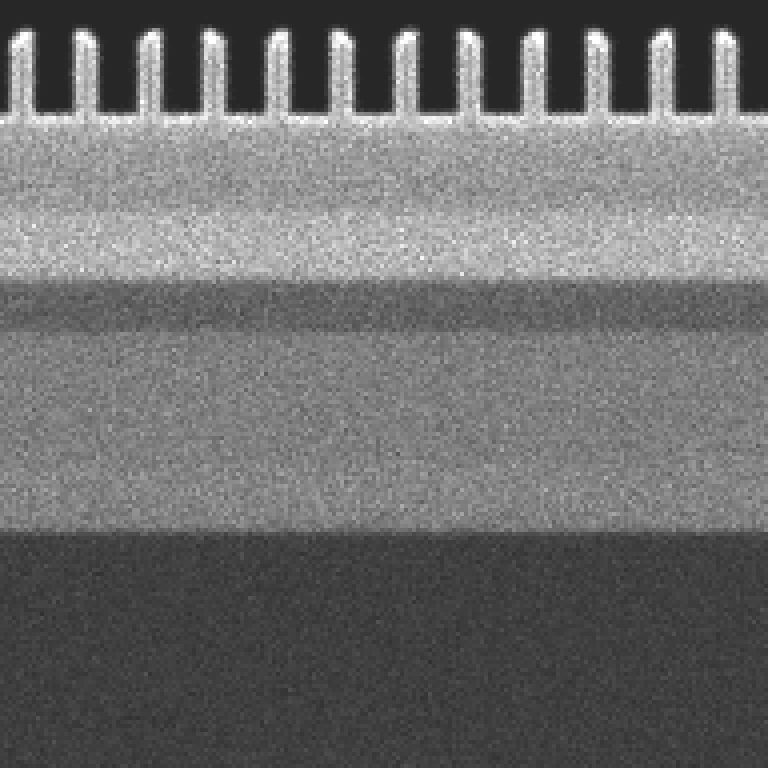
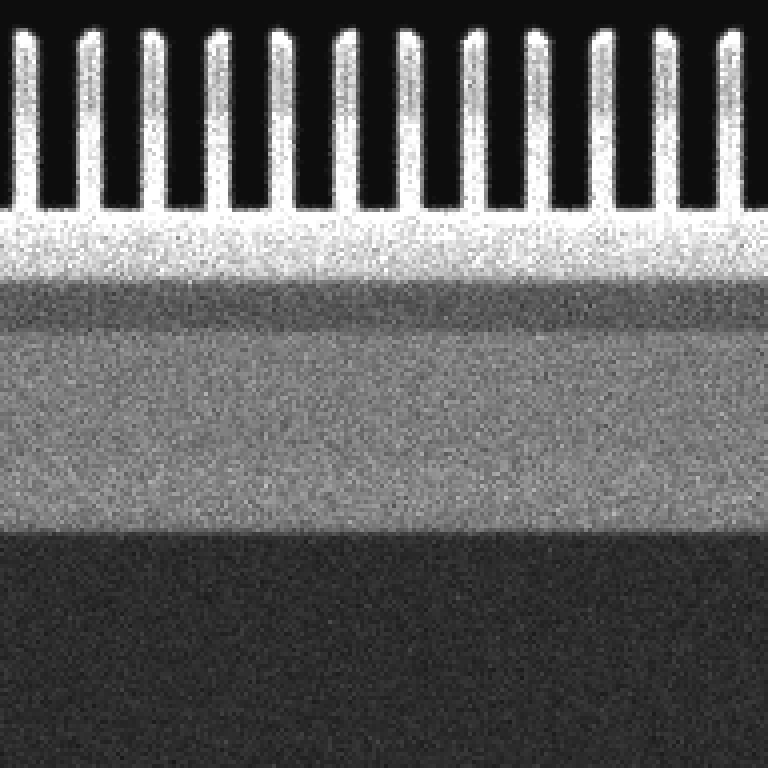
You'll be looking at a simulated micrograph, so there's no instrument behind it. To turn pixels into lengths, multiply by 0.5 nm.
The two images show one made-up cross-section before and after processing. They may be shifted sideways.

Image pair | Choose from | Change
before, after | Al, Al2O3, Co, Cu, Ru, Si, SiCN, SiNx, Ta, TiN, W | Ru (removed)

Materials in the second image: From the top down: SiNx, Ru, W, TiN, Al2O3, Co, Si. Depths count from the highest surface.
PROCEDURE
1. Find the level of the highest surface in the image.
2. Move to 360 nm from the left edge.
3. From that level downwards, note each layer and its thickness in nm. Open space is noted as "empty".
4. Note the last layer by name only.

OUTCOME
empty 4, SiNx 38, Ru 48, W 34, TiN 26, Al2O3 66, Co 34, Si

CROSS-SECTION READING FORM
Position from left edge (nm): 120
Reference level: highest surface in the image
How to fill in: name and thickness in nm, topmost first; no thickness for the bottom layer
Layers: empty 90, W 34, TiN 26, Al2O3 66, Co 34, Si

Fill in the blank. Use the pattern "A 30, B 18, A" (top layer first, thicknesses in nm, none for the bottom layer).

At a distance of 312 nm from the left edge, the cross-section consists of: empty 90, W 34, TiN 26, Al2O3 66, Co 34, Si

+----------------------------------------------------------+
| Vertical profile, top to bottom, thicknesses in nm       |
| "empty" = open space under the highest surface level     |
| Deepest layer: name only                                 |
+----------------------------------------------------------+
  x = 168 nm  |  empty 4, SiNx 38, Ru 48, W 34, TiN 26, Al2O3 66, Co 34, Si